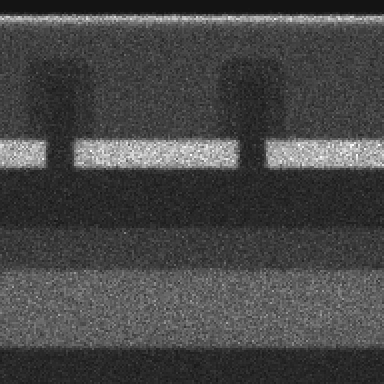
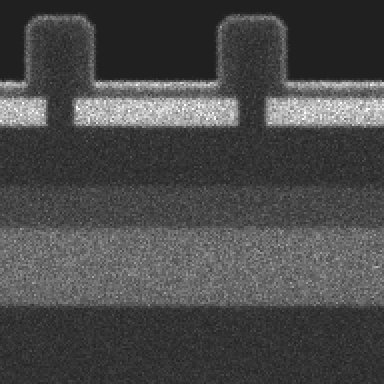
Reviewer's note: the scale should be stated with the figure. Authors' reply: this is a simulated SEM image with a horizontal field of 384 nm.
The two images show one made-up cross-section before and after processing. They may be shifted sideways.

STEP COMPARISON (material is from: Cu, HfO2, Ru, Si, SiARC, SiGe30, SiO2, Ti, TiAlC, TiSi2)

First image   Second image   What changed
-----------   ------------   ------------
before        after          SiARC, removed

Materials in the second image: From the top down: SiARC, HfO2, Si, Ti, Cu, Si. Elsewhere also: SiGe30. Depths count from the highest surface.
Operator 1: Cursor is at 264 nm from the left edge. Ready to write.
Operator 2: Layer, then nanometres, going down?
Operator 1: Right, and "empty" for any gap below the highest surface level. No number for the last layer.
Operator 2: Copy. SiGe30 20, Si 150, Ti 42, Cu 78, Si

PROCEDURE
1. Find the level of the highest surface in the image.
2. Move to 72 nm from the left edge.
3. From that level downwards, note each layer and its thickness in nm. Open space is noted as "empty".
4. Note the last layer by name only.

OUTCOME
SiGe30 20, Si 150, Ti 42, Cu 78, Si